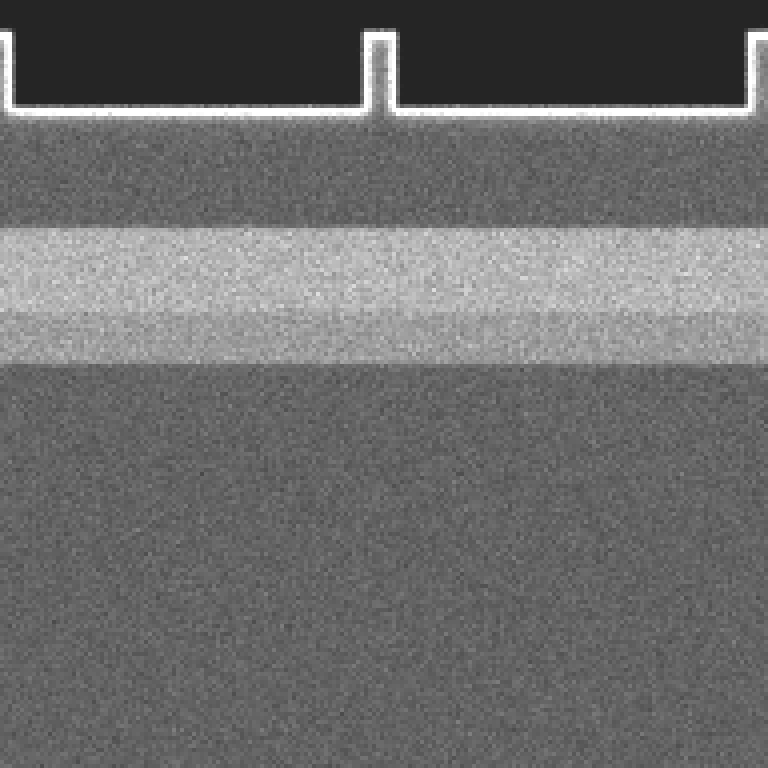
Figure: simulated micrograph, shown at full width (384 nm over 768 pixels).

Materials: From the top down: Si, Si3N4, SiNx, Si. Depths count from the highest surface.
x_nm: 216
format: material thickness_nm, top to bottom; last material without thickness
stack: empty 38, Si 60, Si3N4 42, SiNx 26, Si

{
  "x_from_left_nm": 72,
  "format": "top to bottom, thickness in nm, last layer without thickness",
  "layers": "empty 38, Si 60, Si3N4 42, SiNx 26, Si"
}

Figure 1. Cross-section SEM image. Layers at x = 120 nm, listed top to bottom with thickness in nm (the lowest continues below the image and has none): empty 38, Si 60, Si3N4 42, SiNx 26, Si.